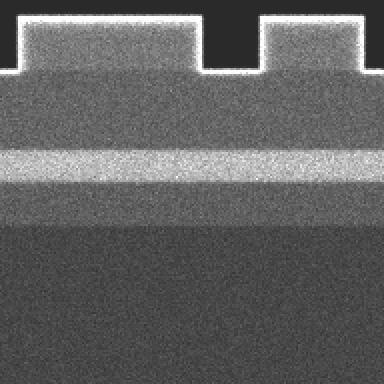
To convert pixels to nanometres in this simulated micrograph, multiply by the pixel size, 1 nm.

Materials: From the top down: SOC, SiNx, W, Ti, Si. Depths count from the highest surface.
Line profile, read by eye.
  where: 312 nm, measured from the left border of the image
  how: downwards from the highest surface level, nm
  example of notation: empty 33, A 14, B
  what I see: SOC 54, SiNx 80, W 32, Ti 44, Si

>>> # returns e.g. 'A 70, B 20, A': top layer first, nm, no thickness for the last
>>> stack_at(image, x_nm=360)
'SOC 54, SiNx 80, W 32, Ti 44, Si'